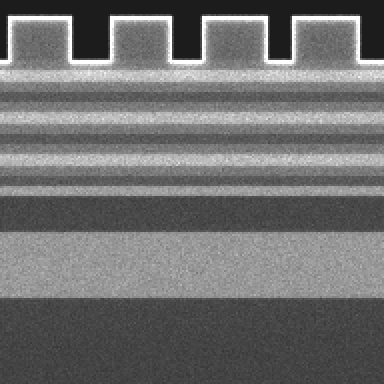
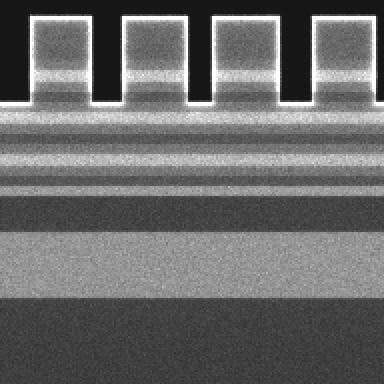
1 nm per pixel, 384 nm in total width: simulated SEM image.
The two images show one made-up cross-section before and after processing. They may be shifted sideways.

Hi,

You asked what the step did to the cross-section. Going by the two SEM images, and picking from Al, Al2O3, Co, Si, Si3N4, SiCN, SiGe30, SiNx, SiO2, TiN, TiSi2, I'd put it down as Co and Si3N4 and SiGe30, removed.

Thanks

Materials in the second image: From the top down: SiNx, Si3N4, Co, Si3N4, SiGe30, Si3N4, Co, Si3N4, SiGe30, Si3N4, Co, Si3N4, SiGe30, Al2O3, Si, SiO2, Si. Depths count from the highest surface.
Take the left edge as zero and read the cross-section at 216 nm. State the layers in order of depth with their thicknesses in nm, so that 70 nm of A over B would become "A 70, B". SiNx 44, Si3N4 10, Co 12, Si3N4 10, SiGe30 10, Si3N4 10, Co 12, Si3N4 10, SiGe30 10, Si3N4 10, Co 12, Si3N4 10, SiGe30 10, Al2O3 10, Si 36, SiO2 66, Si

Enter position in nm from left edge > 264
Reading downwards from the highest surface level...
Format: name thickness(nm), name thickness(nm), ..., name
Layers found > SiNx 44, Si3N4 10, Co 12, Si3N4 10, SiGe30 10, Si3N4 10, Co 12, Si3N4 10, SiGe30 10, Si3N4 10, Co 12, Si3N4 10, SiGe30 10, Al2O3 10, Si 36, SiO2 66, Si